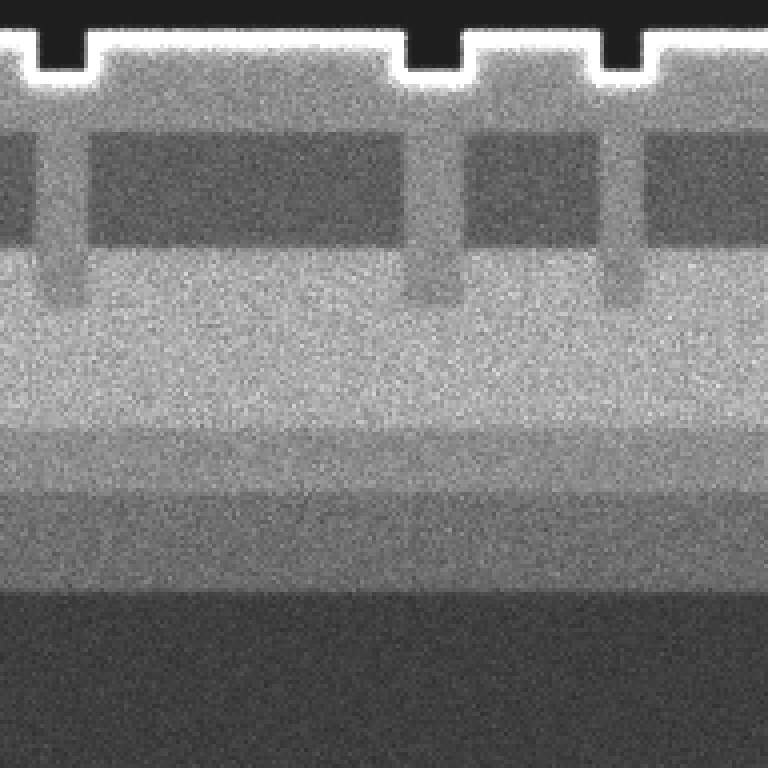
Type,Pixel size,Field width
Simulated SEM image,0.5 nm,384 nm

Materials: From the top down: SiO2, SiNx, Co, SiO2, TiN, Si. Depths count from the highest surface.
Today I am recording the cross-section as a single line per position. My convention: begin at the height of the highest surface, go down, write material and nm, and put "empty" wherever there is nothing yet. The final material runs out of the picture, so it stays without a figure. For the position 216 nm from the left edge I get empty 20, SiO2 118, Co 60, SiO2 32, TiN 50, Si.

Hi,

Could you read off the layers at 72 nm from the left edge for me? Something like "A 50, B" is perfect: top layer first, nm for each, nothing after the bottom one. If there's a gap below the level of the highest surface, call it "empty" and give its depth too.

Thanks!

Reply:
SiO2 50, SiNx 58, Co 90, SiO2 32, TiN 50, Si